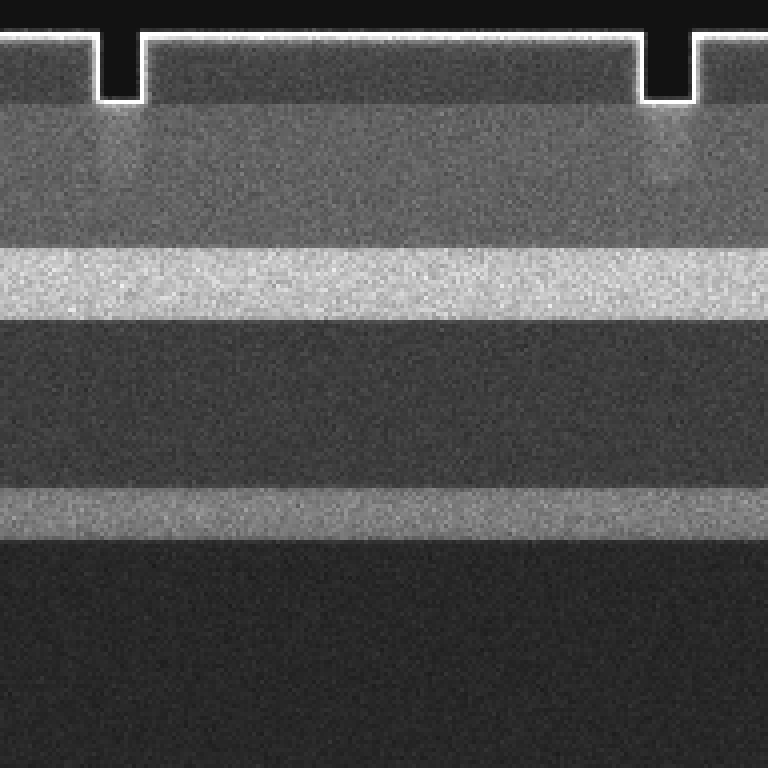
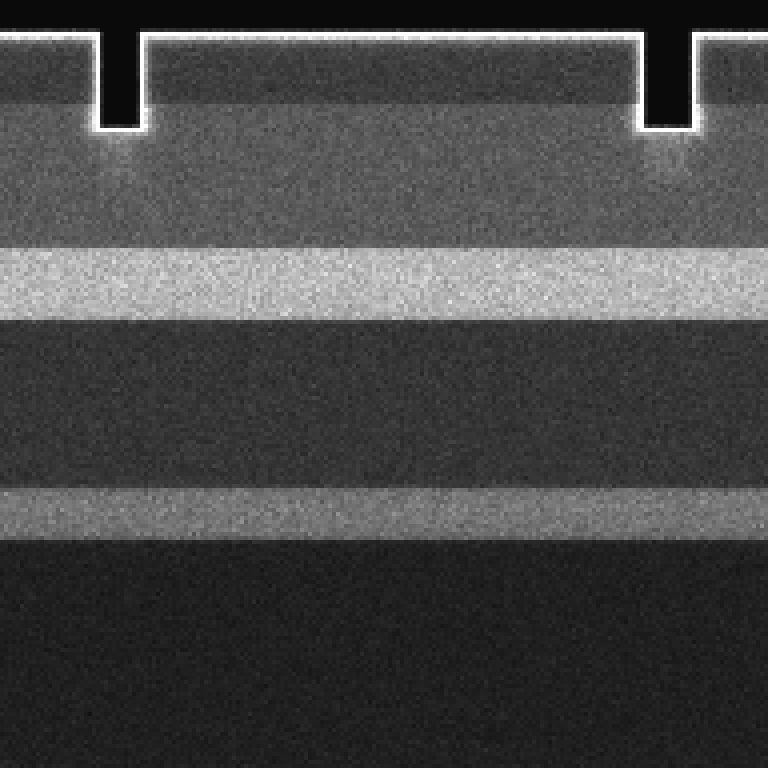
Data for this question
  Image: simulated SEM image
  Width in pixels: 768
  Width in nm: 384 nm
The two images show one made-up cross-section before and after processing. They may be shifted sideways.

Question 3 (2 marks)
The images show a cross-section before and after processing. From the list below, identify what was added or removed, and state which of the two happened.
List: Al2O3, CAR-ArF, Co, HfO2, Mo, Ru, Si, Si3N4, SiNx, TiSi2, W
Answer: Ru was removed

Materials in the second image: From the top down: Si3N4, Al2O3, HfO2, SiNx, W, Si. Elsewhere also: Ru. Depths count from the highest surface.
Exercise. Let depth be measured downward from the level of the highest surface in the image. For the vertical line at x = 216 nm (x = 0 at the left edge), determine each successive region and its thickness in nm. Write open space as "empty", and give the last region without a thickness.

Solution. Si3N4 36, Al2O3 72, HfO2 36, SiNx 84, W 26, Si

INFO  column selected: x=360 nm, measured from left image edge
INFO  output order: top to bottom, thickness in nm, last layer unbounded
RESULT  Si3N4 36, Al2O3 72, HfO2 36, SiNx 84, W 26, Si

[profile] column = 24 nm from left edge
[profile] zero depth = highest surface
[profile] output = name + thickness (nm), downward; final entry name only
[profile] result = Si3N4 36, Al2O3 72, HfO2 36, SiNx 84, W 26, Si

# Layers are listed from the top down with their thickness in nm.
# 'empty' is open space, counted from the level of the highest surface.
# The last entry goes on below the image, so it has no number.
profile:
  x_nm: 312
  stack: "Si3N4 36, Al2O3 72, HfO2 36, SiNx 84, W 26, Si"